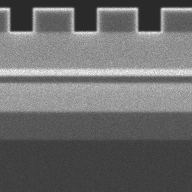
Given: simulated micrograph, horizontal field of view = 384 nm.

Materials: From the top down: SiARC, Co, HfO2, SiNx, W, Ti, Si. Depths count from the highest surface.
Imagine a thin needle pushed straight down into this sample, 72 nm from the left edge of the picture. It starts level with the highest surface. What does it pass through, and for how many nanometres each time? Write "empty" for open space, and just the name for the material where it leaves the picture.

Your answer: SiARC 48, Co 74, HfO2 14, SiNx 14, W 58, Ti 56, Si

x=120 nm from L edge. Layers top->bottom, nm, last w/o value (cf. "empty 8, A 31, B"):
SiARC 48, Co 74, HfO2 14, SiNx 14, W 58, Ti 56, Si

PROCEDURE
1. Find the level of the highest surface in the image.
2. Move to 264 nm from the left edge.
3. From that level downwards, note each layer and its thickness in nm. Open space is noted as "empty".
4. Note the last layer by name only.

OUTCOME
SiARC 48, Co 74, HfO2 14, SiNx 14, W 58, Ti 56, Si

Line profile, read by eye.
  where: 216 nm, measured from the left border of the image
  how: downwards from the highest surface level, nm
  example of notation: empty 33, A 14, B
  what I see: SiARC 48, Co 74, HfO2 14, SiNx 14, W 58, Ti 56, Si